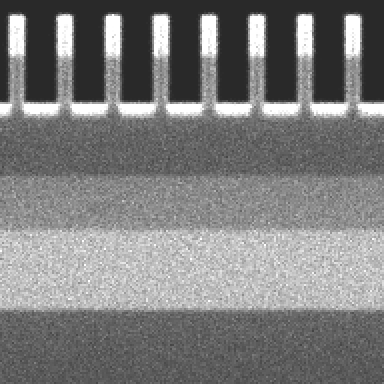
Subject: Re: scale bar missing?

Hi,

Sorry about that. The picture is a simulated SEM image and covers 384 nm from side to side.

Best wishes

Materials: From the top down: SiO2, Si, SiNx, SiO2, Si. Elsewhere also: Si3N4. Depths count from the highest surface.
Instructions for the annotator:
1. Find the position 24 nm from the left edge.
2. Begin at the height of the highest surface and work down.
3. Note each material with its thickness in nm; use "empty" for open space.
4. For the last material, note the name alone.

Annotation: empty 88, SiO2 12, Si 60, SiNx 54, SiO2 80, Si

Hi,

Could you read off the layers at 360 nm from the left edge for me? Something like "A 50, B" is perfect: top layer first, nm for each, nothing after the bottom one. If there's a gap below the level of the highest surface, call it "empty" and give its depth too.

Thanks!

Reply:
empty 88, SiO2 12, Si 60, SiNx 54, SiO2 80, Si